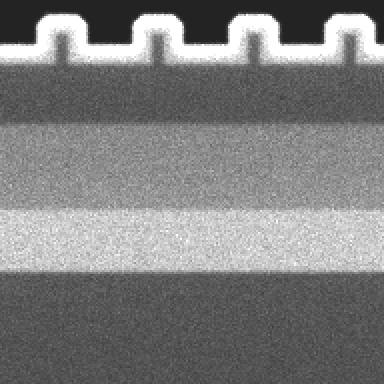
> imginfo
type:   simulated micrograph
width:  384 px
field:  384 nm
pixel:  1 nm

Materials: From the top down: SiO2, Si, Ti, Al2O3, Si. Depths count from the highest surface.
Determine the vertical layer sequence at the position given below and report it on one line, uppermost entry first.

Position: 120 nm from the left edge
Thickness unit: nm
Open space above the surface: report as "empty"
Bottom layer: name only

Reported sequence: empty 30, SiO2 18, Si 60, Ti 86, Al2O3 62, Si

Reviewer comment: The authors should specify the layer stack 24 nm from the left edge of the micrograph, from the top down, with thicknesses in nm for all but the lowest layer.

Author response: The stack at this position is empty 30, SiO2 18, Si 60, Ti 86, Al2O3 62, Si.